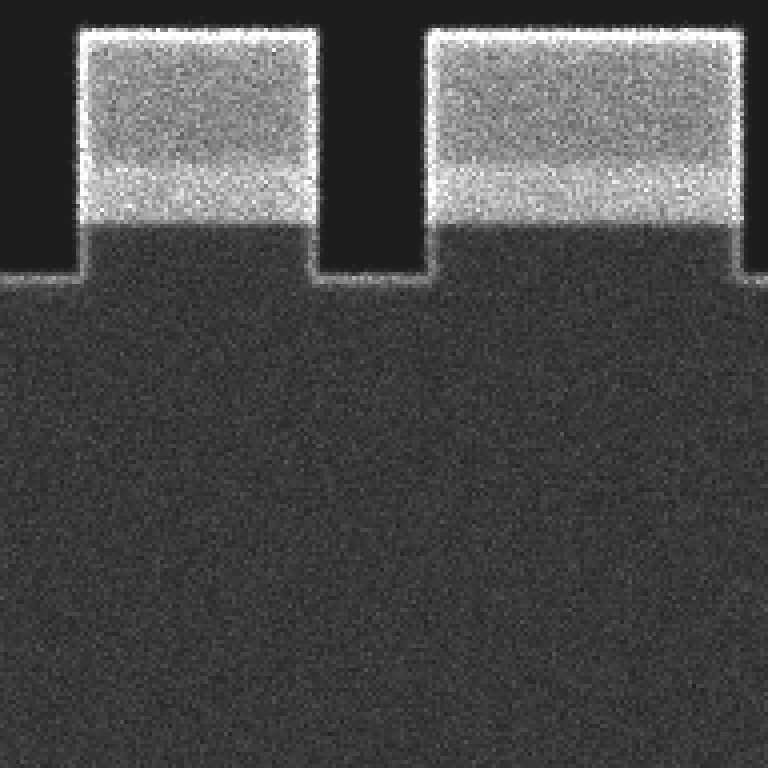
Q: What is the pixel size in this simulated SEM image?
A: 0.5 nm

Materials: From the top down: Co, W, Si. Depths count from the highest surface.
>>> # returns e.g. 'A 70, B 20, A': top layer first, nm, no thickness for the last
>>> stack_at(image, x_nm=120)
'Co 66, W 30, Si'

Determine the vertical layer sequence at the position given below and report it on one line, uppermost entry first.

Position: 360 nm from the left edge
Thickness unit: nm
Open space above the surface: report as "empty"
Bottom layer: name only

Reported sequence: Co 66, W 30, Si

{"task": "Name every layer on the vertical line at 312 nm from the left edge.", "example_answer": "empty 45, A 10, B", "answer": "Co 66, W 30, Si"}